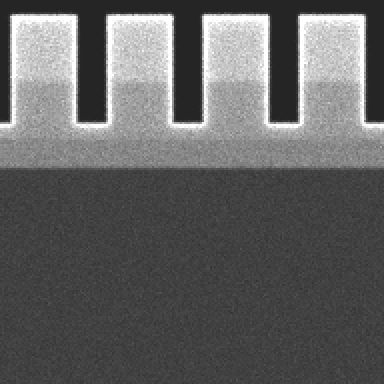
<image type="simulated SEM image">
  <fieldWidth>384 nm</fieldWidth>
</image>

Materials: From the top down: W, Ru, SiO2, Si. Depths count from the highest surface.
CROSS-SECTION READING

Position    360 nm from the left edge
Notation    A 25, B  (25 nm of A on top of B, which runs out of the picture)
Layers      W 66, Ru 58, SiO2 28, Si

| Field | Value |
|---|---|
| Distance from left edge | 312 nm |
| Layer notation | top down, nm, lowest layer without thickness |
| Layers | W 66, Ru 58, SiO2 28, Si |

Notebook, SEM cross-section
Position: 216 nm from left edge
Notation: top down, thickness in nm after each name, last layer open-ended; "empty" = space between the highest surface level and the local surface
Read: W 66, Ru 58, SiO2 28, Si